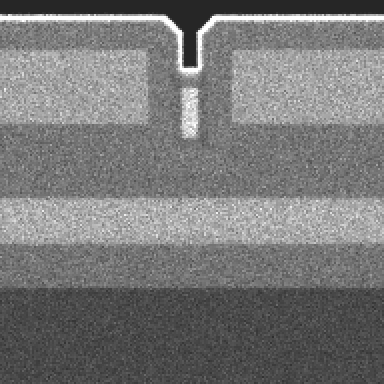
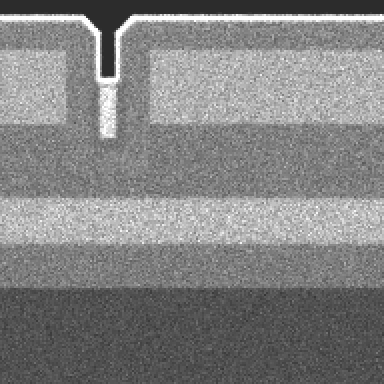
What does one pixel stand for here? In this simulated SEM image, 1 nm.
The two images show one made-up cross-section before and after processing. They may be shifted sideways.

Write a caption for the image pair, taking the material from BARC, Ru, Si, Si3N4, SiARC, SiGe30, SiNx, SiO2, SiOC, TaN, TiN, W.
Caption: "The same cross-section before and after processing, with SiARC removed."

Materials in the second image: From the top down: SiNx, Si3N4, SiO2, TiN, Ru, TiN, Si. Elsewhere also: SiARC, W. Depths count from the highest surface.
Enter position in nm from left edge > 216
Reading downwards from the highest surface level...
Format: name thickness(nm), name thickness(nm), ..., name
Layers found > SiNx 10, Si3N4 24, SiO2 74, TiN 74, Ru 46, TiN 44, Si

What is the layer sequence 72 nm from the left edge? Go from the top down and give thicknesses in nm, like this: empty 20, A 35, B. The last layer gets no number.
SiNx 10, Si3N4 146, TiN 26, Ru 46, TiN 44, Si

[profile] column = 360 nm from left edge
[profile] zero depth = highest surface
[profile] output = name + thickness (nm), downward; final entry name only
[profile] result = SiNx 10, Si3N4 24, SiO2 74, TiN 74, Ru 46, TiN 44, Si